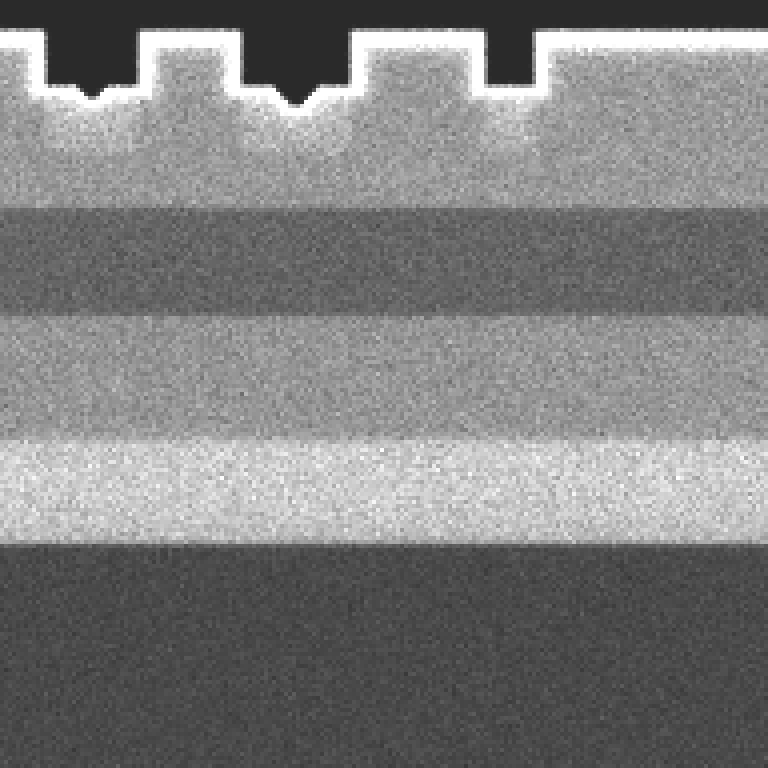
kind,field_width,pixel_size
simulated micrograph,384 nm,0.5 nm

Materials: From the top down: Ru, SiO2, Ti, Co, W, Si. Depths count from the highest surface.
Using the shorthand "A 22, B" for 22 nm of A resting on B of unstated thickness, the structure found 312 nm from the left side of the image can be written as SiO2 88, Ti 54, Co 62, W 52, Si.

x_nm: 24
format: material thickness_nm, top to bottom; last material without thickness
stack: empty 28, Ru 32, SiO2 28, Ti 54, Co 62, W 52, Si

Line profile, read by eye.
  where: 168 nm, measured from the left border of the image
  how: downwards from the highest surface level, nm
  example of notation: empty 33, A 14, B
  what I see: empty 28, Ru 32, SiO2 28, Ti 54, Co 62, W 52, Si